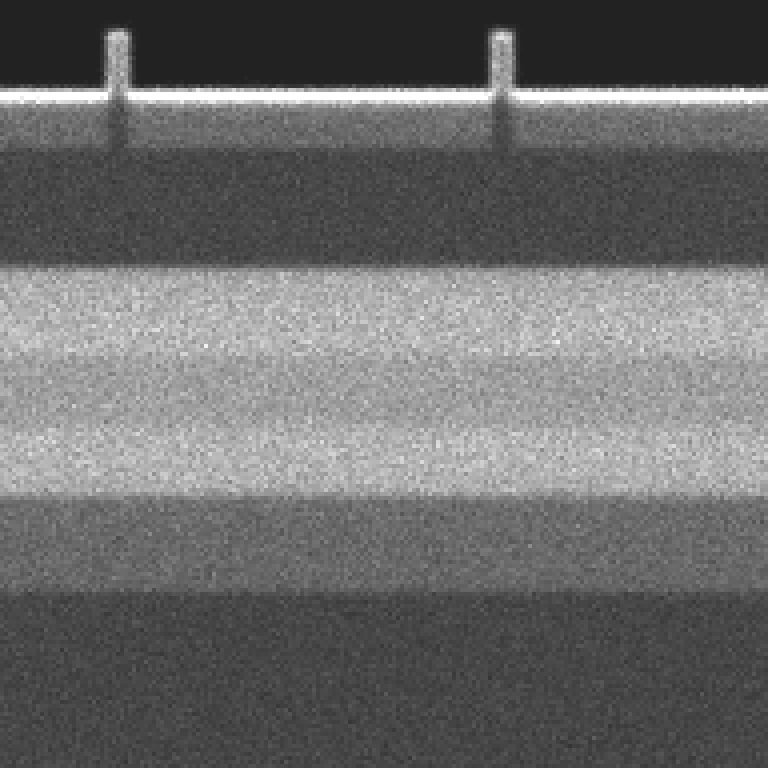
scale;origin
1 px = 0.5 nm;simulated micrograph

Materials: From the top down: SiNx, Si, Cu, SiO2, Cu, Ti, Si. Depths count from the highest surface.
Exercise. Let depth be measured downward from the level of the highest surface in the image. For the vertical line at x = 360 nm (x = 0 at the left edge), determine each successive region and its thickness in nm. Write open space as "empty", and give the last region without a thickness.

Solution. empty 30, SiNx 28, Si 60, Cu 44, SiO2 36, Cu 34, Ti 48, Si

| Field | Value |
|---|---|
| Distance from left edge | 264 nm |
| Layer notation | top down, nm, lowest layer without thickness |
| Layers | empty 30, SiNx 28, Si 60, Cu 44, SiO2 36, Cu 34, Ti 48, Si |